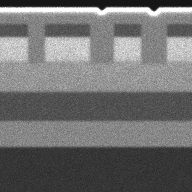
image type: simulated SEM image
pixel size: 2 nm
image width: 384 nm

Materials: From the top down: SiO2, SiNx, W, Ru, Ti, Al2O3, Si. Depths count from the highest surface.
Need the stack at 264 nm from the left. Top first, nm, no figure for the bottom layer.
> SiO2 32, SiNx 26, W 48, Ru 62, Ti 58, Al2O3 52, Si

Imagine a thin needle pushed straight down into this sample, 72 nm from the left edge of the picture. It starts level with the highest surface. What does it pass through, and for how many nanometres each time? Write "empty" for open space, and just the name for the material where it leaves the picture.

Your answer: SiO2 112, Ru 56, Ti 58, Al2O3 52, Si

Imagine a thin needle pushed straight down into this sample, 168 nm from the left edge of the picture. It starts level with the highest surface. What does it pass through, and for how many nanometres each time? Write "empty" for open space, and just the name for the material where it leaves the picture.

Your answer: SiO2 32, SiNx 26, W 48, Ru 62, Ti 58, Al2O3 52, Si